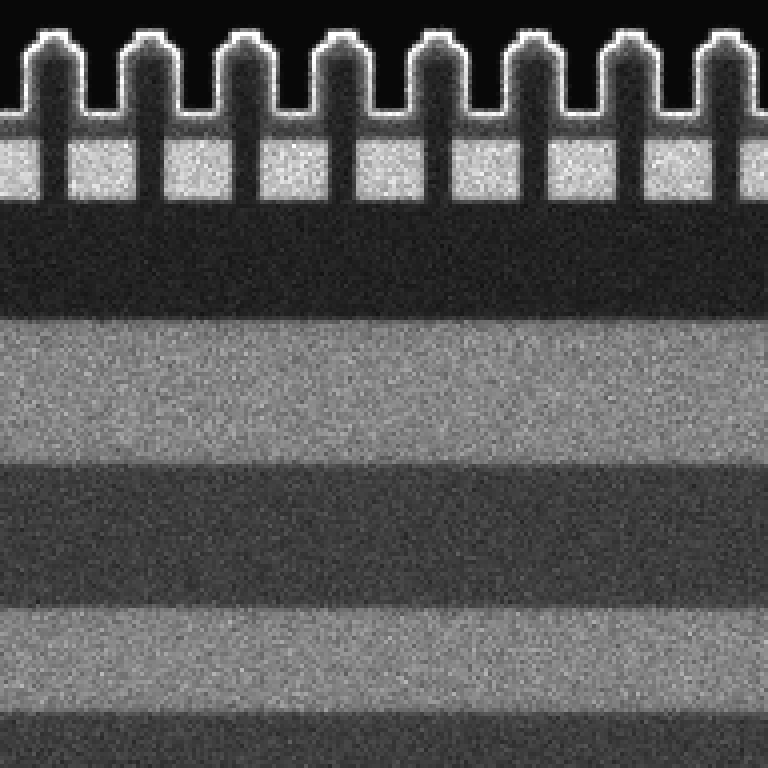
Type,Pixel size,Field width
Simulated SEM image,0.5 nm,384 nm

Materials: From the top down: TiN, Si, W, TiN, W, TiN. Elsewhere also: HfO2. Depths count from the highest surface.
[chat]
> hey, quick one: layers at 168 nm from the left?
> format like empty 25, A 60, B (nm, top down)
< TiN 14, Si 130, W 72, TiN 72, W 52, TiN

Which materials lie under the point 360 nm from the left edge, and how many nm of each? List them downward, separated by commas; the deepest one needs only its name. TiN 14, Si 130, W 72, TiN 72, W 52, TiN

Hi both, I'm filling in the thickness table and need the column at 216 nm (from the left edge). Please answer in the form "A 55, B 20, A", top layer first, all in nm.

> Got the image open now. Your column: TiN 14, Si 130, W 72, TiN 72, W 52, TiN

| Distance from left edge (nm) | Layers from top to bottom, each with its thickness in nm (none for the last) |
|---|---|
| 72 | TiN 14, Si 130, W 72, TiN 72, W 52, TiN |